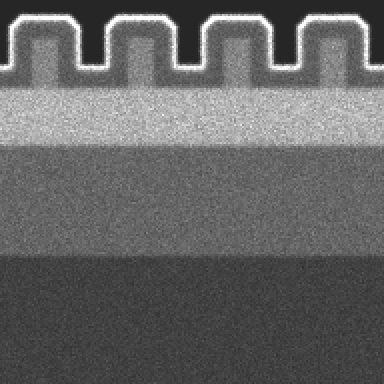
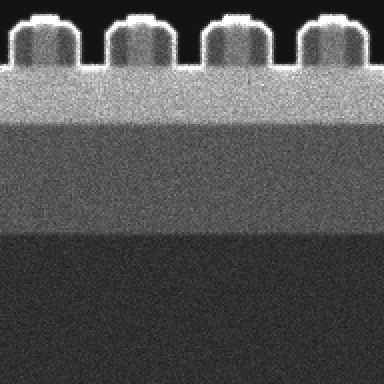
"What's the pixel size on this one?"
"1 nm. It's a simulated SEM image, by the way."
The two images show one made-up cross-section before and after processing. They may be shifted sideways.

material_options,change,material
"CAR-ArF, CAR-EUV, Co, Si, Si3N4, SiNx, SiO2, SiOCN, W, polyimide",removed,SiNx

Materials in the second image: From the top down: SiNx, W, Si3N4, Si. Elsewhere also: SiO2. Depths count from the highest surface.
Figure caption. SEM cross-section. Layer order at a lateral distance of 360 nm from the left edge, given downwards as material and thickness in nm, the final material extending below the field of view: empty 10, SiNx 40, W 58, Si3N4 110, Si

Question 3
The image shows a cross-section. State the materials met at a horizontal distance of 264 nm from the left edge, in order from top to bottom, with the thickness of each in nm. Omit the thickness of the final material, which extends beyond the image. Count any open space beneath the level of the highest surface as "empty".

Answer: empty 10, SiNx 40, W 58, Si3N4 110, Si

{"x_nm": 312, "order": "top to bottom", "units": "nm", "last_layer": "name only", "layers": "empty 6, SiNx 44, W 58, Si3N4 110, Si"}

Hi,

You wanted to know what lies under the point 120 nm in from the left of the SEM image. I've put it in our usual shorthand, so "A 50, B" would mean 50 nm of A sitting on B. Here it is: empty 6, SiNx 44, W 58, Si3N4 110, Si